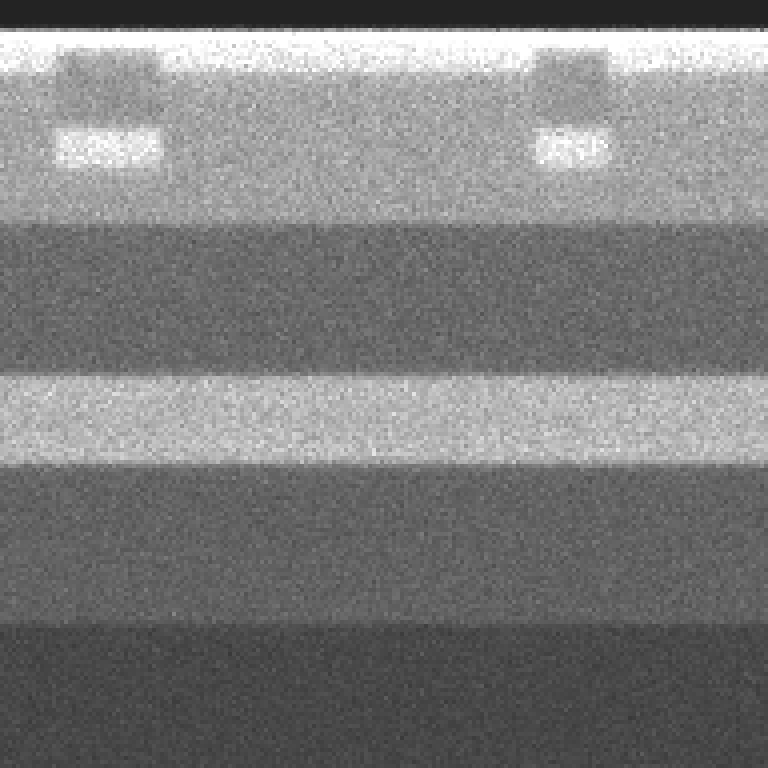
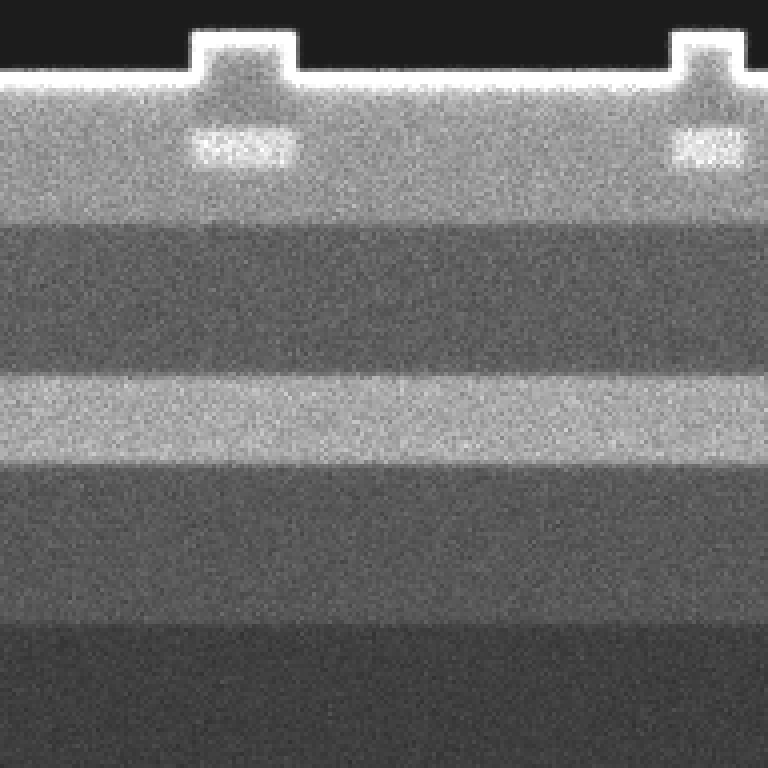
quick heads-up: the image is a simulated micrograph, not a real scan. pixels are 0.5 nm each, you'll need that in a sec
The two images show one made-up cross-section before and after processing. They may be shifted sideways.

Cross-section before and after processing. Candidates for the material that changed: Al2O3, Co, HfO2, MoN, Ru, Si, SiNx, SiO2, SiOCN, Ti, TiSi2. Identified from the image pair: Co (removed).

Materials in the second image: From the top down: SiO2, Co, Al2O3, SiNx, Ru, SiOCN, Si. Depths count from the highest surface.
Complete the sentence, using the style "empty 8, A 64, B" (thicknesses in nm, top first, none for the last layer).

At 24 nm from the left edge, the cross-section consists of empty 20, Al2O3 76, SiNx 76, Ru 44, SiOCN 80, Si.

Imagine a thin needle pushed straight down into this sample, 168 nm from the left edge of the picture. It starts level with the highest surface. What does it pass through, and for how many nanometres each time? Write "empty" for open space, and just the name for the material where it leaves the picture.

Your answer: empty 20, Al2O3 76, SiNx 76, Ru 44, SiOCN 80, Si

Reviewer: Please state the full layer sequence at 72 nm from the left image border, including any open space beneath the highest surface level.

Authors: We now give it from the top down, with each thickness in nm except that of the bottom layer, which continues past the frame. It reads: empty 20, Al2O3 76, SiNx 76, Ru 44, SiOCN 80, Si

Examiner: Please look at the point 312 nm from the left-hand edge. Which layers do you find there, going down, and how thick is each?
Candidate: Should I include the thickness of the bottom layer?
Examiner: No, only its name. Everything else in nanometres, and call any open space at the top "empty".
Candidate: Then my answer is empty 20, Al2O3 76, SiNx 76, Ru 44, SiOCN 80, Si